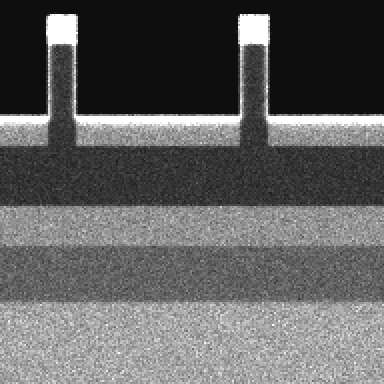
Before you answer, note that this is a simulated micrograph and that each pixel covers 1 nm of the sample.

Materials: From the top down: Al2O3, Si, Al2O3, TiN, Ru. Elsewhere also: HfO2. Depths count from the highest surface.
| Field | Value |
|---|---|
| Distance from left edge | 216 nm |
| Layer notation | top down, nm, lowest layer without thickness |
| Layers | empty 100, Al2O3 30, Si 60, Al2O3 40, TiN 56, Ru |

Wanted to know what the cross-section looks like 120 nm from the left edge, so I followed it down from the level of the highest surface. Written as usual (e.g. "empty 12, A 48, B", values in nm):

empty 100, Al2O3 30, Si 60, Al2O3 40, TiN 56, Ru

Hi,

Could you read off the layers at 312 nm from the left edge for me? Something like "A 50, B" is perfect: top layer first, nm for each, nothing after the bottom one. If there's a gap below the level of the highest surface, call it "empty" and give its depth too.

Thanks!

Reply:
empty 100, Al2O3 30, Si 60, Al2O3 40, TiN 56, Ru